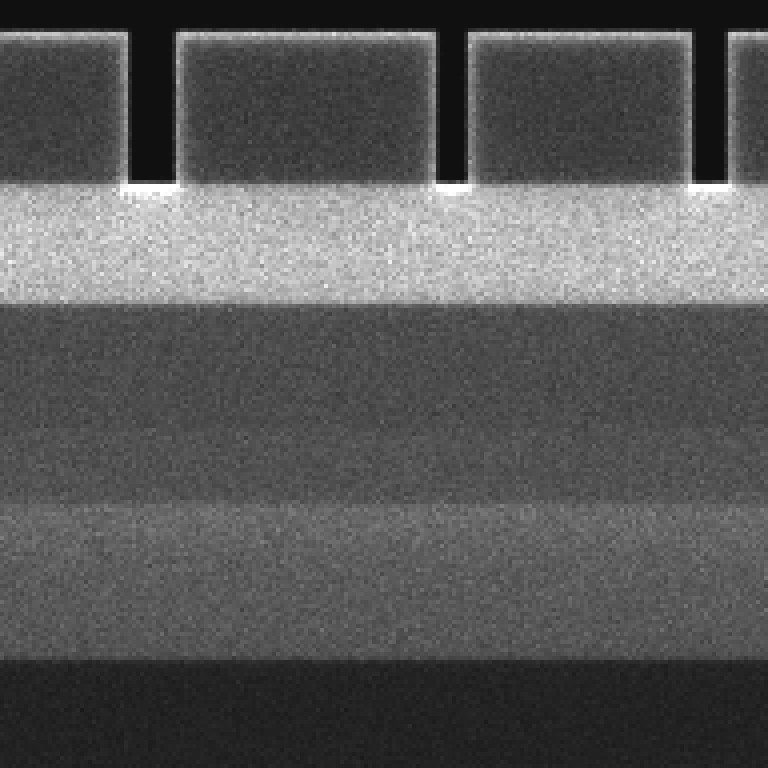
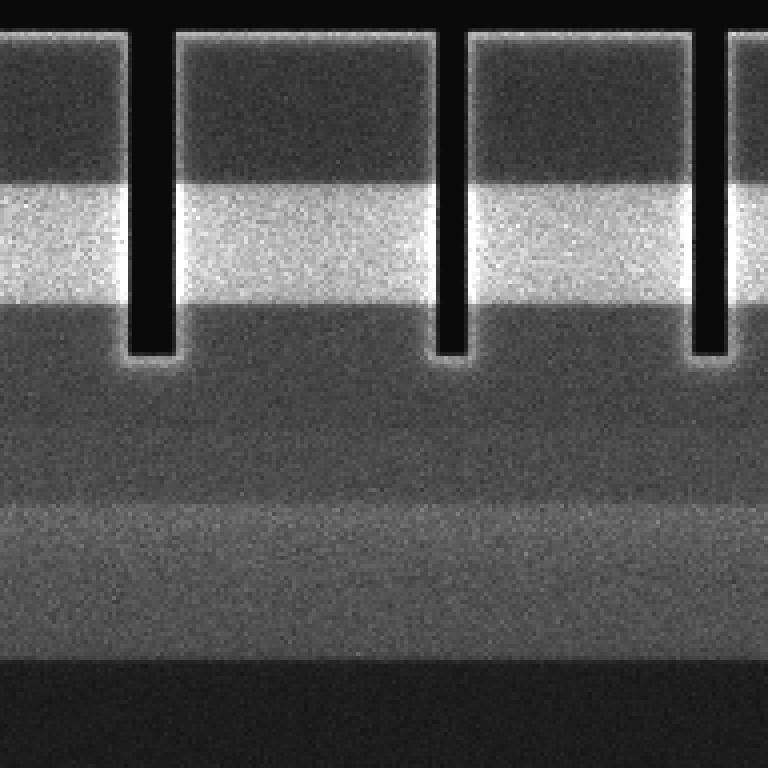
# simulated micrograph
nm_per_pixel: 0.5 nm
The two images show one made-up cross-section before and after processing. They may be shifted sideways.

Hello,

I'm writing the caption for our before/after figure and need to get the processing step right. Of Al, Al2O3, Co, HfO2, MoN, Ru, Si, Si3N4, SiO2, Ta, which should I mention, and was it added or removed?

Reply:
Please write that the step removed HfO2 and SiO2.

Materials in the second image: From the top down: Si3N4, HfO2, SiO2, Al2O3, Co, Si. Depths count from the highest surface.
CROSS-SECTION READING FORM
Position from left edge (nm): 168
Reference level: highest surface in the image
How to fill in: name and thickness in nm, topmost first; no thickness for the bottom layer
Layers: Si3N4 76, HfO2 60, SiO2 62, Al2O3 38, Co 78, Si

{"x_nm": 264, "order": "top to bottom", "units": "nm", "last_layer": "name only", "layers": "Si3N4 76, HfO2 60, SiO2 62, Al2O3 38, Co 78, Si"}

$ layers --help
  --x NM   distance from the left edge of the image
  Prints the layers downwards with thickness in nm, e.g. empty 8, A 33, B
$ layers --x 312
Si3N4 76, HfO2 60, SiO2 62, Al2O3 38, Co 78, Si